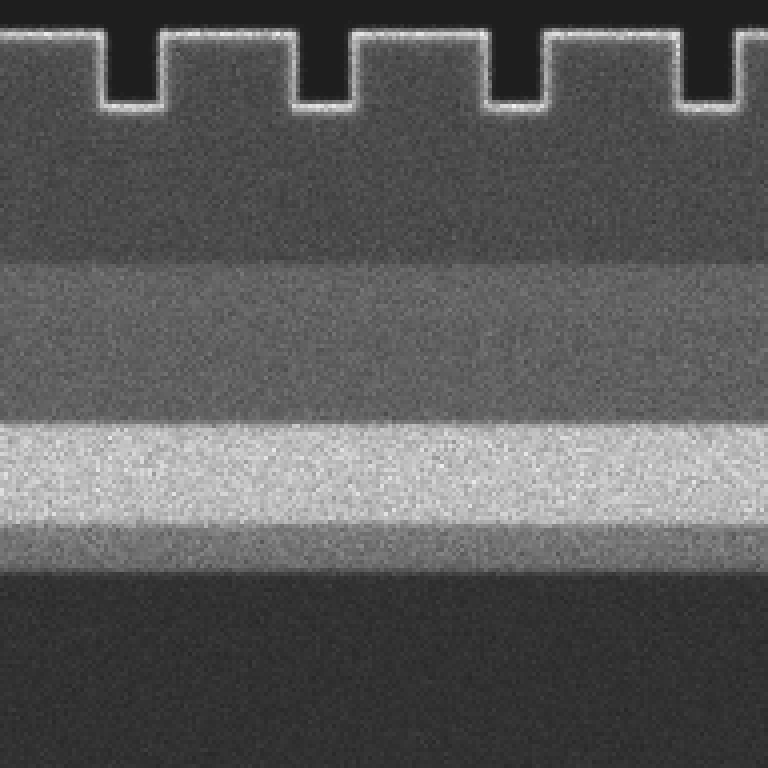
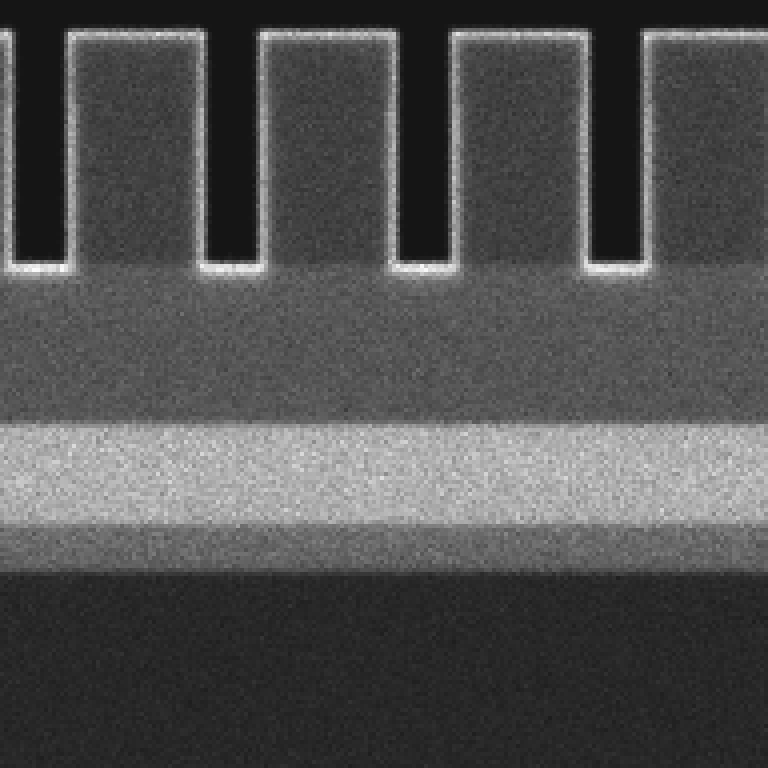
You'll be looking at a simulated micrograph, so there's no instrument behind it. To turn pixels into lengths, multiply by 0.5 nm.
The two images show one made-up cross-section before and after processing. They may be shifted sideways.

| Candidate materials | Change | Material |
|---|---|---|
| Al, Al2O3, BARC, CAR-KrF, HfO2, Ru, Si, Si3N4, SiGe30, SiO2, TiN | removed | Si3N4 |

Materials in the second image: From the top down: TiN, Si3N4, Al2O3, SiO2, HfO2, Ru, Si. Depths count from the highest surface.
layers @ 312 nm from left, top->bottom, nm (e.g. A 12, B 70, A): empty 116, Al2O3 26, SiO2 54, HfO2 50, Ru 24, Si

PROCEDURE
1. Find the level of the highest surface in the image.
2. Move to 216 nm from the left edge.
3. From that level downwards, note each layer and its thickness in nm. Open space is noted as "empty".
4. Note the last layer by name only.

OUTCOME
empty 116, Al2O3 26, SiO2 54, HfO2 50, Ru 24, Si